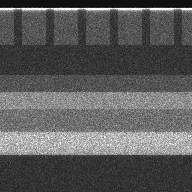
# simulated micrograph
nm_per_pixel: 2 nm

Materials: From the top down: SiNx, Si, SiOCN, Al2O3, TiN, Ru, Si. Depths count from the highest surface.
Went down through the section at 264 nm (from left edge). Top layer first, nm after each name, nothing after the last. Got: SiNx 74, Si 60, SiOCN 34, Al2O3 34, TiN 46, Ru 46, Si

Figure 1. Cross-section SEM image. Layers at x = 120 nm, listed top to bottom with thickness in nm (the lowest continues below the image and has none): SiNx 74, Si 60, SiOCN 34, Al2O3 34, TiN 46, Ru 46, Si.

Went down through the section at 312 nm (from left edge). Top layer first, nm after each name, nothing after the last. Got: SiNx 74, Si 60, SiOCN 34, Al2O3 34, TiN 46, Ru 46, Si